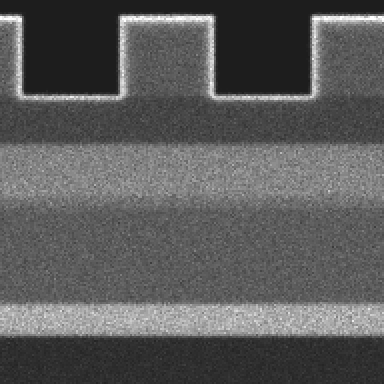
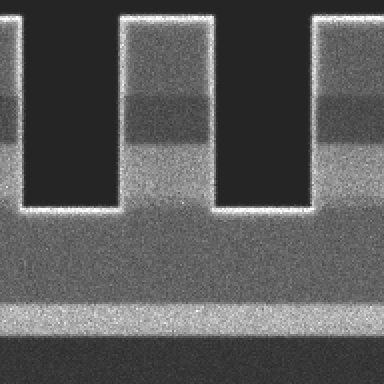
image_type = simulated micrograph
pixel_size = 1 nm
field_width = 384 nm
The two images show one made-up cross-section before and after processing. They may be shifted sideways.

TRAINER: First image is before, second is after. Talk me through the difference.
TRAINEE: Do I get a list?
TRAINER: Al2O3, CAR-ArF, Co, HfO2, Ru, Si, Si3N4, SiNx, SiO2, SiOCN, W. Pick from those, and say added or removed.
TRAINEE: removed: Ru and Si3N4 and W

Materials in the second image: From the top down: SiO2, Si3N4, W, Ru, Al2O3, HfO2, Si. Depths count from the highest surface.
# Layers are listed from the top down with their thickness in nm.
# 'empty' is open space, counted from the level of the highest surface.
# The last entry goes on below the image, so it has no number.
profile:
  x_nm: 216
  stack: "empty 192, Al2O3 96, HfO2 32, Si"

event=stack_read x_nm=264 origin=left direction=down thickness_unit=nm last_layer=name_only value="empty 192, Al2O3 96, HfO2 32, Si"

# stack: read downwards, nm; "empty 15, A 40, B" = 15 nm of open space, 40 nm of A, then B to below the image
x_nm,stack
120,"SiO2 80, Si3N4 48, W 52, Ru 12, Al2O3 96, HfO2 32, Si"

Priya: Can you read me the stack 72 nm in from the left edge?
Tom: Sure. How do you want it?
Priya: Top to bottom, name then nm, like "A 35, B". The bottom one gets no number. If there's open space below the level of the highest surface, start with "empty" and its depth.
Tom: empty 192, Al2O3 96, HfO2 32, Si